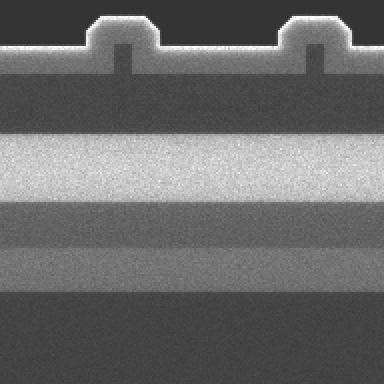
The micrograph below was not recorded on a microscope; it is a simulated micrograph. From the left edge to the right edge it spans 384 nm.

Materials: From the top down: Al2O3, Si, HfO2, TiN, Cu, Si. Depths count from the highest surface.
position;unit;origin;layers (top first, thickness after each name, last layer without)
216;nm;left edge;empty 30, Al2O3 28, Si 60, HfO2 68, TiN 46, Cu 44, Si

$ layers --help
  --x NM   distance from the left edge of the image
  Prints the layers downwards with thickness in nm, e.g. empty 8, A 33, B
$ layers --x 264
empty 30, Al2O3 28, Si 60, HfO2 68, TiN 46, Cu 44, Si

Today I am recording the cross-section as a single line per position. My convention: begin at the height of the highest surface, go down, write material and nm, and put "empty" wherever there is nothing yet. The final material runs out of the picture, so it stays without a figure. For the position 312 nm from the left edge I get Al2O3 28, Si 90, HfO2 68, TiN 46, Cu 44, Si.